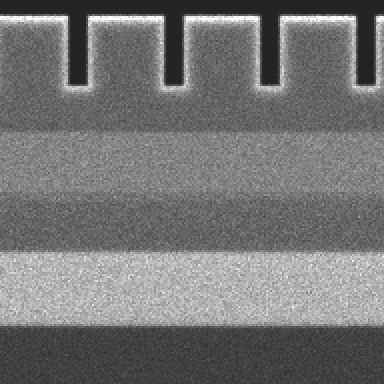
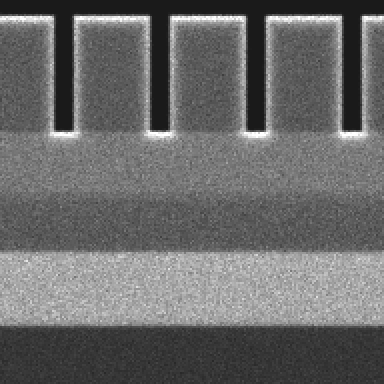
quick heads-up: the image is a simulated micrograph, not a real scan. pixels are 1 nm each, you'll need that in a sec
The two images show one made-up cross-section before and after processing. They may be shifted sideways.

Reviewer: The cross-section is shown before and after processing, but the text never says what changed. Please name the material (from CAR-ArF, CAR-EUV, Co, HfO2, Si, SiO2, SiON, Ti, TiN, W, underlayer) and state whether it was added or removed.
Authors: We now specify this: underlayer, removed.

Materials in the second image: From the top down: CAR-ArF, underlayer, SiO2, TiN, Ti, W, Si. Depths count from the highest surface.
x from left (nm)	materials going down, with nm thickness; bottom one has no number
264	empty 116, SiO2 60, TiN 8, Ti 52, W 74, Si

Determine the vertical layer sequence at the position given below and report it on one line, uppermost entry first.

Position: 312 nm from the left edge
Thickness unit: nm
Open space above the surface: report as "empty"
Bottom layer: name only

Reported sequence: CAR-ArF 70, underlayer 46, SiO2 60, TiN 8, Ti 52, W 74, Si